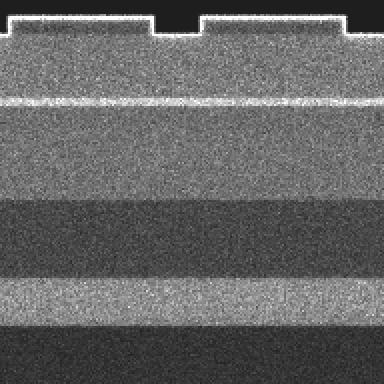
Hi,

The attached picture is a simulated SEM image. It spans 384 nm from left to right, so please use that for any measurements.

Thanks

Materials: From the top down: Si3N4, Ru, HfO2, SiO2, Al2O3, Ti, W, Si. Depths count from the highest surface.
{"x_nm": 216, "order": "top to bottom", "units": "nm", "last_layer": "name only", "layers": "Si3N4 18, Ru 64, HfO2 8, SiO2 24, Al2O3 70, Ti 78, W 48, Si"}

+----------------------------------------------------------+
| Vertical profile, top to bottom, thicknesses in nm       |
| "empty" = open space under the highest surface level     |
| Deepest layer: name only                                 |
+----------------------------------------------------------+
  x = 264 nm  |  Si3N4 18, Ru 64, HfO2 8, SiO2 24, Al2O3 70, Ti 78, W 48, Si